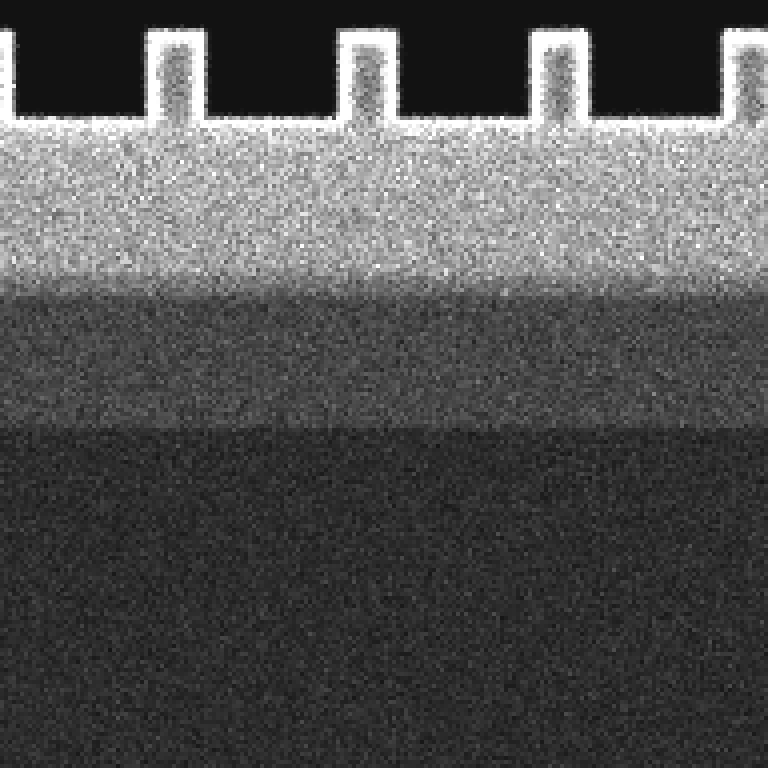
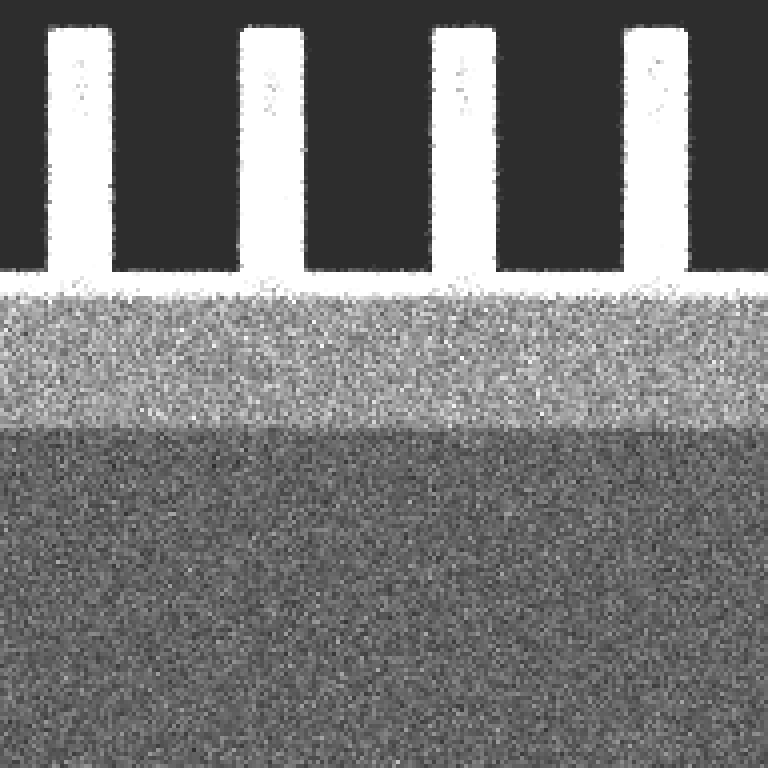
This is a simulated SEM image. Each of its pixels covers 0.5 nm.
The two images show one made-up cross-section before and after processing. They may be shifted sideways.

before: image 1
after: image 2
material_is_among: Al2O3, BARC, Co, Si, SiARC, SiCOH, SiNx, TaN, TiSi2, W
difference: W, removed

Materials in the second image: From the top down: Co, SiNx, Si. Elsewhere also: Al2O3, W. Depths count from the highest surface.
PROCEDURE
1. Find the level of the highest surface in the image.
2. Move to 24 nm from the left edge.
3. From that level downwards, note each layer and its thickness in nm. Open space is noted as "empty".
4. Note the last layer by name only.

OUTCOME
empty 122, Co 10, SiNx 66, Si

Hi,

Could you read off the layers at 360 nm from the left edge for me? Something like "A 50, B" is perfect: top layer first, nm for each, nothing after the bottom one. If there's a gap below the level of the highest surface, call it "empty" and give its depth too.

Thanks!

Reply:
empty 122, Co 10, SiNx 66, Si